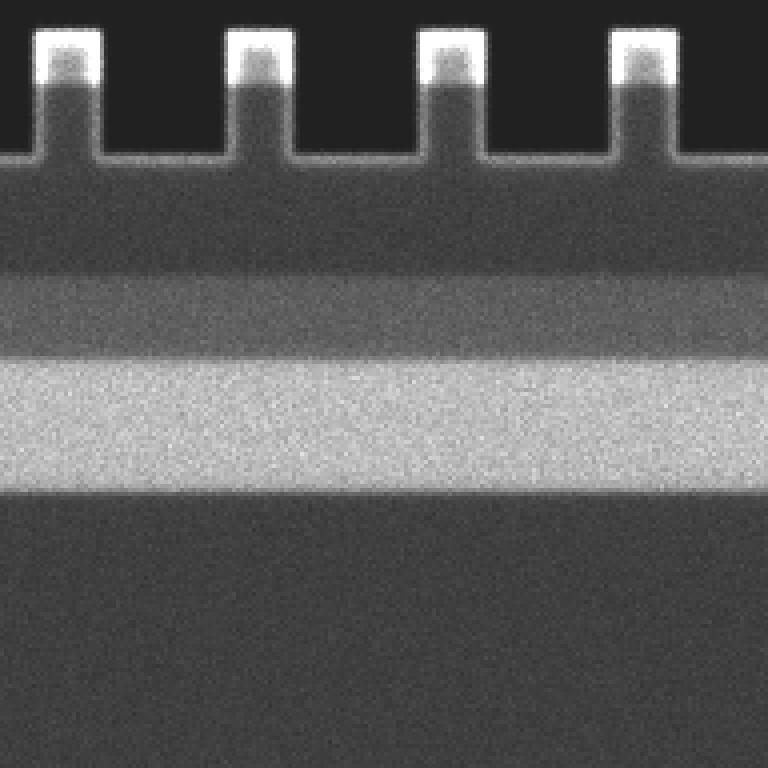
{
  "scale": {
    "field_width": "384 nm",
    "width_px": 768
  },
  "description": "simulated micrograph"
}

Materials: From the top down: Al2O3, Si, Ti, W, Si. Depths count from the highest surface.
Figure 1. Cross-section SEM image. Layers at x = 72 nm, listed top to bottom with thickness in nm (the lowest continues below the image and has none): empty 62, Si 60, Ti 42, W 66, Si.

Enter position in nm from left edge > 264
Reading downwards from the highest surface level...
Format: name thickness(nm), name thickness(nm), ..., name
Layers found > empty 62, Si 60, Ti 42, W 66, Si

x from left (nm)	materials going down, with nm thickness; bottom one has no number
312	Al2O3 26, Si 96, Ti 42, W 66, Si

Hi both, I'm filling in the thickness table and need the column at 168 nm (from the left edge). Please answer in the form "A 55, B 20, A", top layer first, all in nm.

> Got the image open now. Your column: empty 62, Si 60, Ti 42, W 66, Si